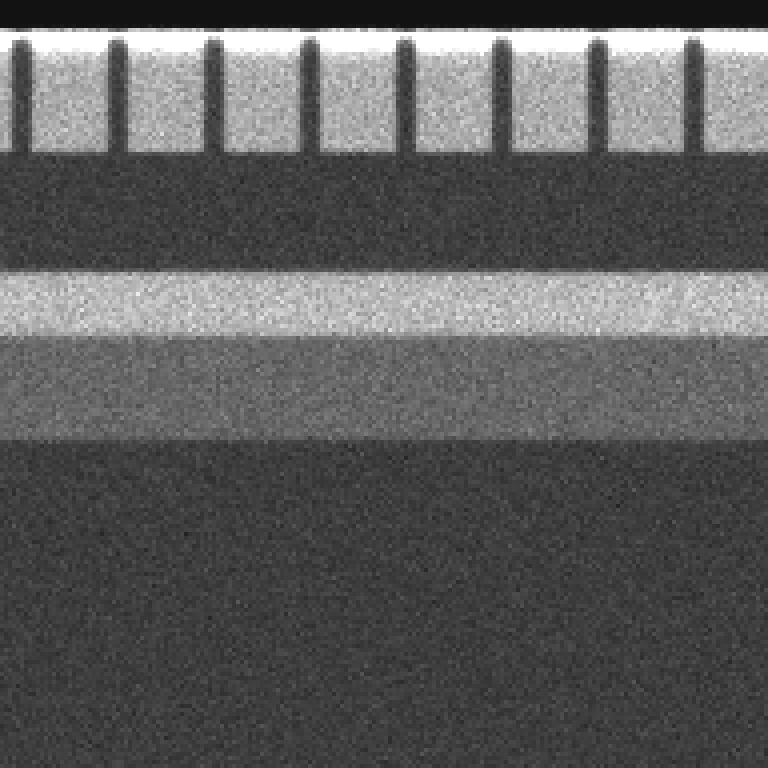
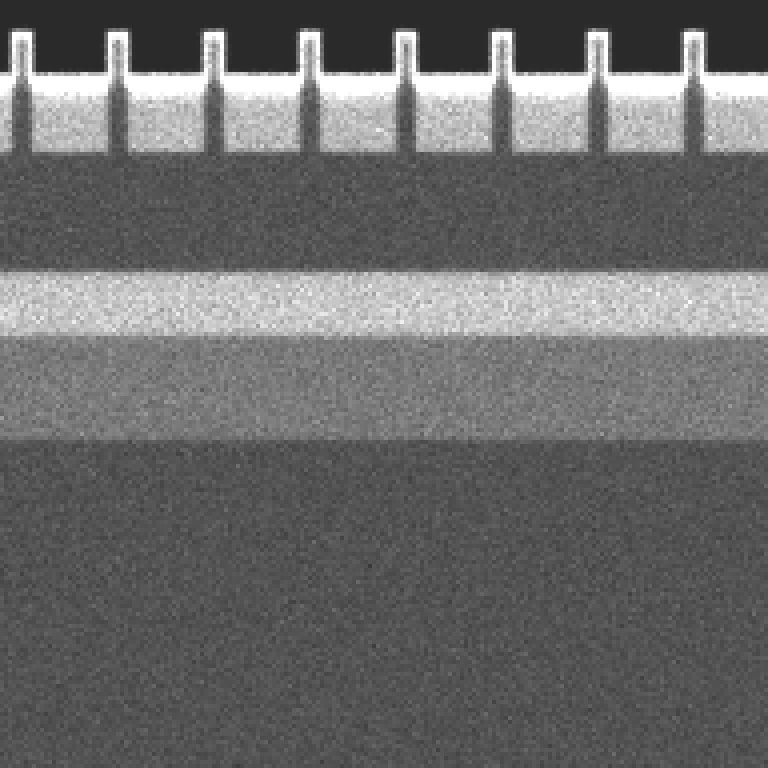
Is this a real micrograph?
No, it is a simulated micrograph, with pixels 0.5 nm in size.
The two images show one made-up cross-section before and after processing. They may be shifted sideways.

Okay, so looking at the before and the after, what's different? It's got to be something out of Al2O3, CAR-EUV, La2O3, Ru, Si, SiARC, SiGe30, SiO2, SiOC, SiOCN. SiO2, removed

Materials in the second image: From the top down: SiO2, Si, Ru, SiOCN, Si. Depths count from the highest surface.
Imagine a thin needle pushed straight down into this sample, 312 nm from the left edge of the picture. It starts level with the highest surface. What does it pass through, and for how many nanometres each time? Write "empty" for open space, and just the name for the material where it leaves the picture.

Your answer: empty 22, SiO2 38, Si 60, Ru 32, SiOCN 52, Si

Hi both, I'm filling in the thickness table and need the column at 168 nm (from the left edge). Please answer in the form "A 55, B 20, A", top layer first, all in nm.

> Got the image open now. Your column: empty 22, SiO2 38, Si 60, Ru 32, SiOCN 52, Si